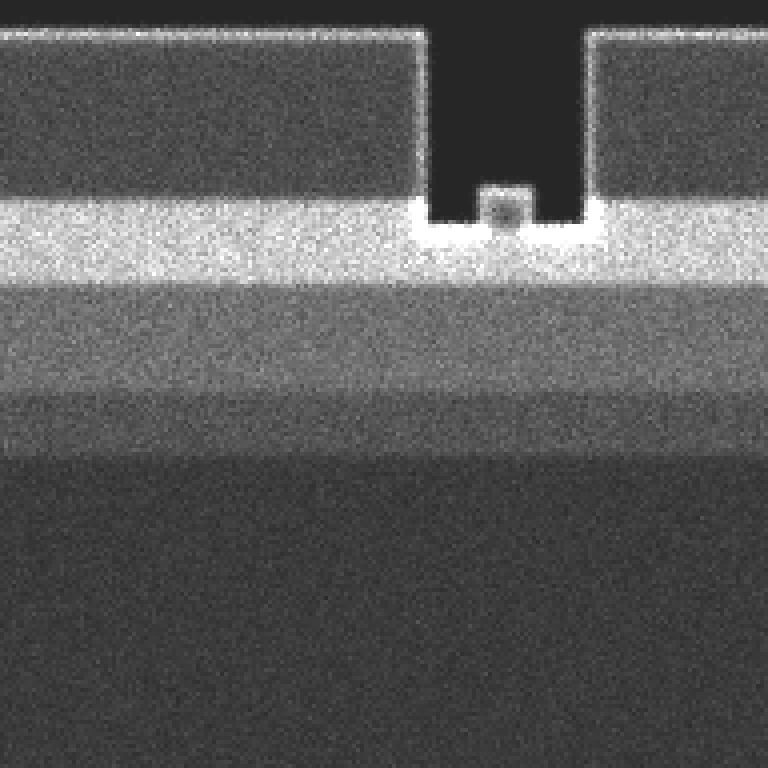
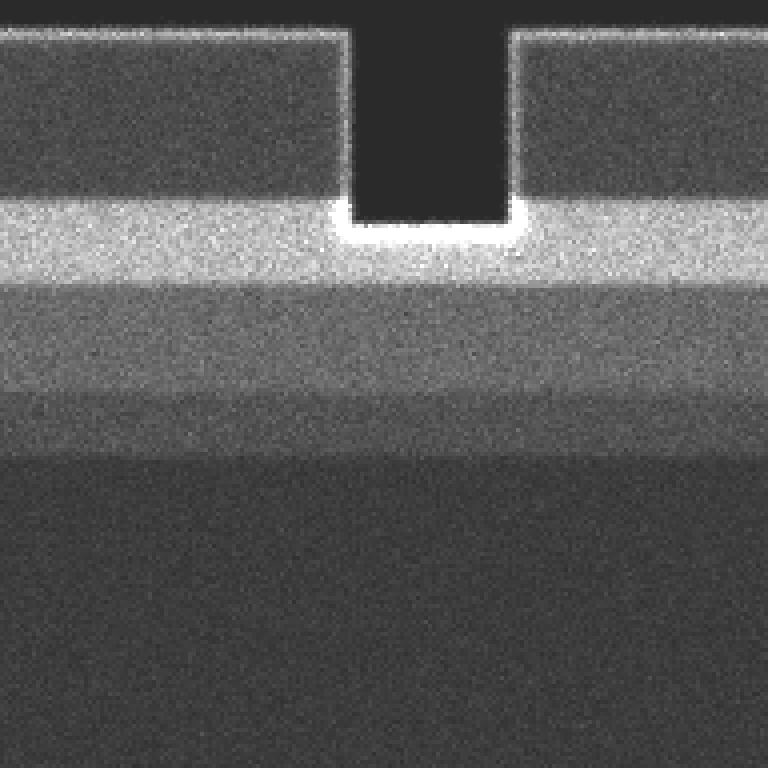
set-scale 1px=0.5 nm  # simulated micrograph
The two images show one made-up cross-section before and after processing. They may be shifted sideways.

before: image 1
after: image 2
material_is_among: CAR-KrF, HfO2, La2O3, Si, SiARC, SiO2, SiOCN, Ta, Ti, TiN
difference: SiARC, removed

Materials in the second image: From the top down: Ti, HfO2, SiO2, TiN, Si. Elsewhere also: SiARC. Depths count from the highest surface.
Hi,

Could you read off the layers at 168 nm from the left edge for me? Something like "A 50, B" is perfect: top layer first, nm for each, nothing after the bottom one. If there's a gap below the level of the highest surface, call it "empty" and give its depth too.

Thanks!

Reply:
Ti 84, HfO2 42, SiO2 54, TiN 32, Si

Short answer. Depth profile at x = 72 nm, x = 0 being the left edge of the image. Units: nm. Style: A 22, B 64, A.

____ Ti 84, HfO2 42, SiO2 54, TiN 32, Si